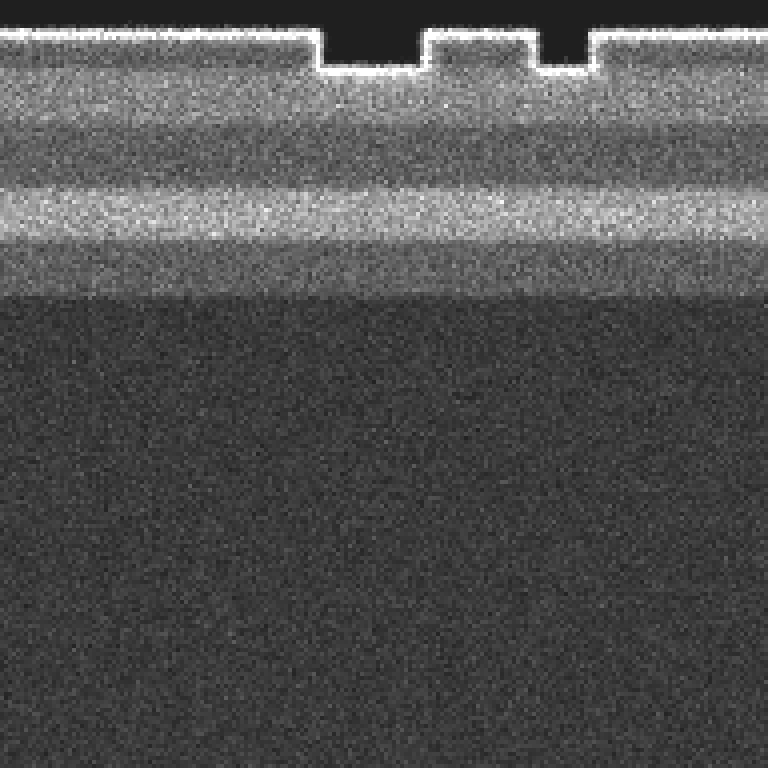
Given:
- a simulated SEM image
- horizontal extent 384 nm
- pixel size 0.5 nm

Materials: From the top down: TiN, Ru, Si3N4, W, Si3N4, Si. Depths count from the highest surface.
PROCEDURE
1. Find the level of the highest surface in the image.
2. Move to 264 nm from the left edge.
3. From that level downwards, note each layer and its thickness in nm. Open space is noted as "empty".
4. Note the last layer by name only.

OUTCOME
TiN 18, Ru 28, Si3N4 32, W 26, Si3N4 28, Si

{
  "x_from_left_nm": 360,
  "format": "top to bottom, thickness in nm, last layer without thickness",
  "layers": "TiN 18, Ru 28, Si3N4 32, W 26, Si3N4 28, Si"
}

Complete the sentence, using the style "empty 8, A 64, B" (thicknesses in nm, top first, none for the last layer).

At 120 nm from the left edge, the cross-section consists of TiN 18, Ru 28, Si3N4 32, W 26, Si3N4 28, Si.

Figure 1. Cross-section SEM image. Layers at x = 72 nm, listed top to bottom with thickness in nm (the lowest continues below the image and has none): TiN 18, Ru 28, Si3N4 32, W 26, Si3N4 28, Si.